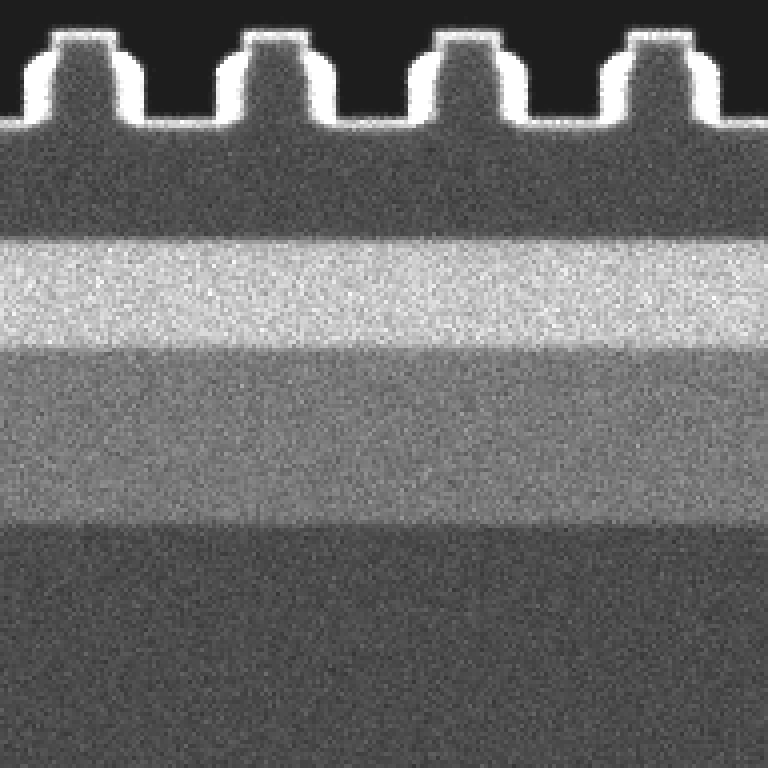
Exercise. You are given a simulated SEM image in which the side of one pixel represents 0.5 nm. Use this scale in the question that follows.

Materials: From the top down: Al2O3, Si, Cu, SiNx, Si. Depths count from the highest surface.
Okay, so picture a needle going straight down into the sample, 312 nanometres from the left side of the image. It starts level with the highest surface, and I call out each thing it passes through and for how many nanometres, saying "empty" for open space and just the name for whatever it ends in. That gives empty 12, Al2O3 32, Si 60, Cu 54, SiNx 88, Si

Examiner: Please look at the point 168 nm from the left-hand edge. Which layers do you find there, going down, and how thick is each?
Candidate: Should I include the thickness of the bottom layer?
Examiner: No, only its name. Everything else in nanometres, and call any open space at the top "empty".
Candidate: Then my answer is empty 44, Si 60, Cu 54, SiNx 88, Si